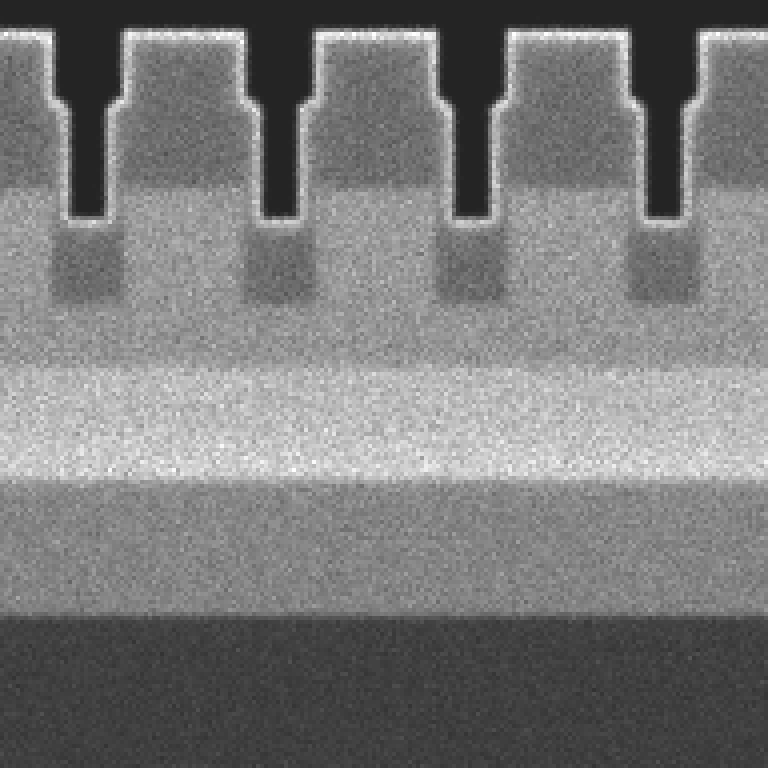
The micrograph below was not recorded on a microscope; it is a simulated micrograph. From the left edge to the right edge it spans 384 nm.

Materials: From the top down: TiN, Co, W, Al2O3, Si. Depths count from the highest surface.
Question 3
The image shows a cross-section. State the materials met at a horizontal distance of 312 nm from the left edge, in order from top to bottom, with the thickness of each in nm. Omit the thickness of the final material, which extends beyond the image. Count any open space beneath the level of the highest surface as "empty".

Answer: TiN 78, Co 90, W 56, Al2O3 68, Si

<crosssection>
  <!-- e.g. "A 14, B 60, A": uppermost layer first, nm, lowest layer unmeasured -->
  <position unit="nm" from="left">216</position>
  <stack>TiN 78, Co 90, W 56, Al2O3 68, Si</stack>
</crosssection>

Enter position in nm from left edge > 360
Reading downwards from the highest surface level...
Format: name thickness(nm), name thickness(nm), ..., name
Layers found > TiN 78, Co 90, W 56, Al2O3 68, Si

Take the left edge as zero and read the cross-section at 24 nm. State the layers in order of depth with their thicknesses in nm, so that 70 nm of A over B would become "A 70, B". TiN 78, Co 90, W 56, Al2O3 68, Si